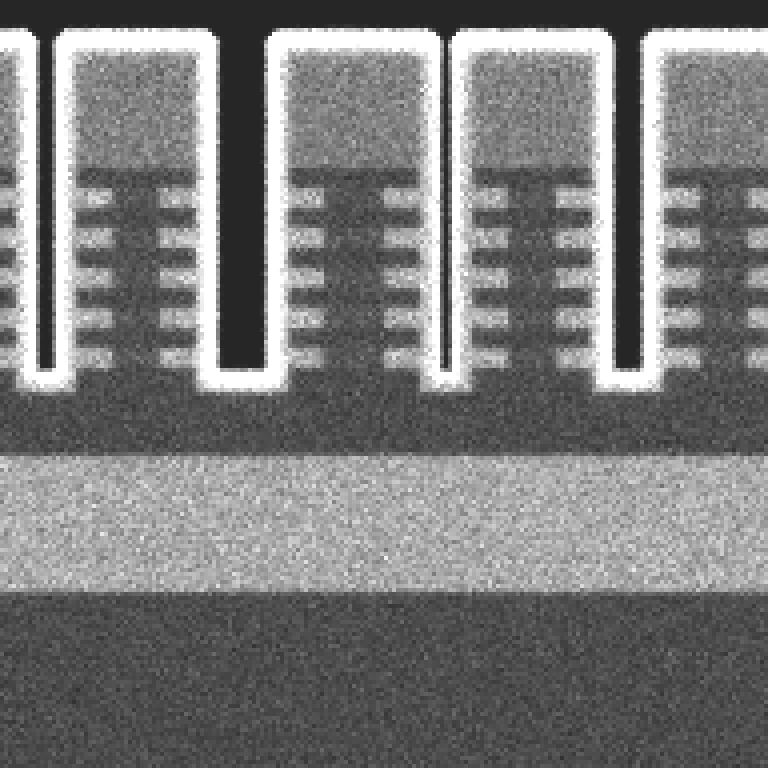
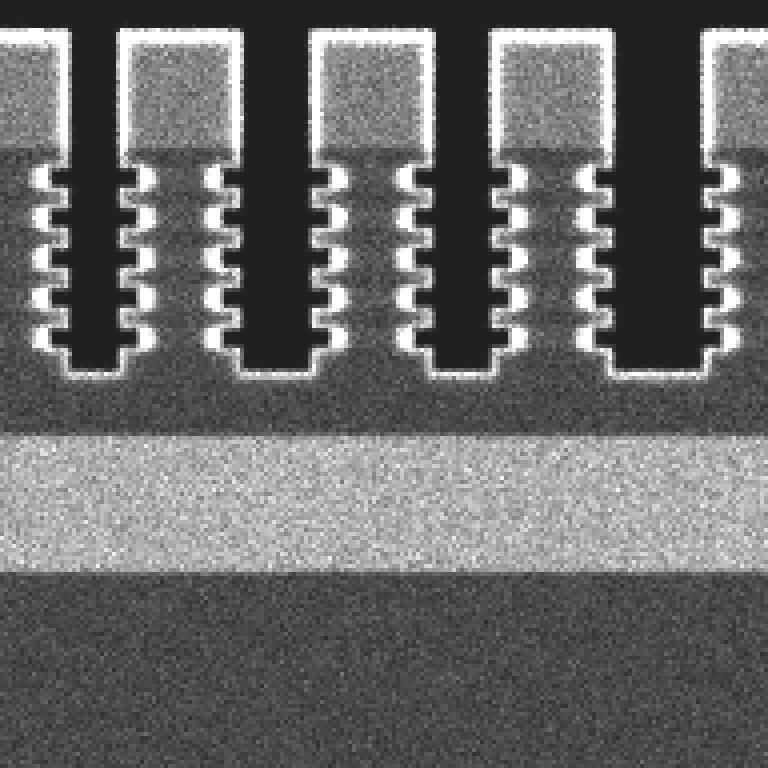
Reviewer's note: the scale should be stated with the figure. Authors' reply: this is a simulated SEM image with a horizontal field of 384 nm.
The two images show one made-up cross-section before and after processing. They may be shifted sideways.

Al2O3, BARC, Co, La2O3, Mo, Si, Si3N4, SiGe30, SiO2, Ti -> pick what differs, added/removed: Al2O3 removed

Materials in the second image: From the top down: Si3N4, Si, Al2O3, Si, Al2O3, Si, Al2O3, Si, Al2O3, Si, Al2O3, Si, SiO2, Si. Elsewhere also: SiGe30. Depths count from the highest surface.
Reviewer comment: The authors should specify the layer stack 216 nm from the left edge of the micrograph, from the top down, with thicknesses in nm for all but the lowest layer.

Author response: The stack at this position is empty 170, Si 32, SiO2 68, Si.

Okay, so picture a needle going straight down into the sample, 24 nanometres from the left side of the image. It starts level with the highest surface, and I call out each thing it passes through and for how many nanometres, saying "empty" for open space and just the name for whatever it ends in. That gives Si3N4 58, Si 10, empty 10, Si 10, empty 10, Si 10, empty 10, Si 10, empty 10, Si 10, empty 10, Si 44, SiO2 68, Si